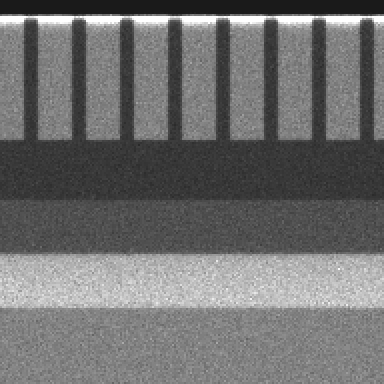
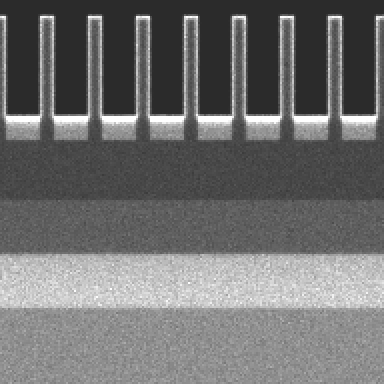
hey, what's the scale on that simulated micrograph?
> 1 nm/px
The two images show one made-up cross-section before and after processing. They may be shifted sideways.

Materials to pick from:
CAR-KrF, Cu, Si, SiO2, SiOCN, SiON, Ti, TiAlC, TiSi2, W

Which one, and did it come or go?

SiO2 - removed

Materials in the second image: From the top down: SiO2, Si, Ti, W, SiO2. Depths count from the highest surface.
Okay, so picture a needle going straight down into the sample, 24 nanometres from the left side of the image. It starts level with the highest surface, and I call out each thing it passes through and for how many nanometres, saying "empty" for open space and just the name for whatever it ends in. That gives empty 100, SiO2 24, Si 60, Ti 54, W 54, SiO2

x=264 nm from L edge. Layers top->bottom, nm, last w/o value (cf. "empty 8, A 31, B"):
empty 100, SiO2 24, Si 60, Ti 54, W 54, SiO2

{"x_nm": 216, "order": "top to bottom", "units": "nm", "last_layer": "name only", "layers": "empty 100, SiO2 24, Si 60, Ti 54, W 54, SiO2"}